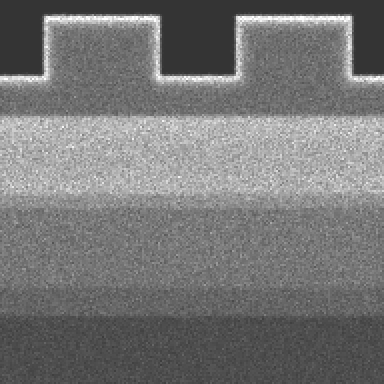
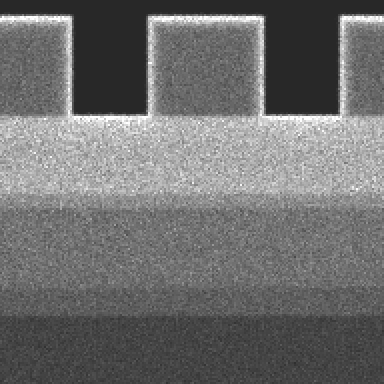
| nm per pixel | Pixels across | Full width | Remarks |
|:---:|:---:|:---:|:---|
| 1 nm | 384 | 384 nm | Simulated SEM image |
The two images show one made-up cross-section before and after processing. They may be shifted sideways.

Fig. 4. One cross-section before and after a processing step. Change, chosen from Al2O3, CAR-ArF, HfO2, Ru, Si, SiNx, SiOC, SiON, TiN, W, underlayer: underlayer removed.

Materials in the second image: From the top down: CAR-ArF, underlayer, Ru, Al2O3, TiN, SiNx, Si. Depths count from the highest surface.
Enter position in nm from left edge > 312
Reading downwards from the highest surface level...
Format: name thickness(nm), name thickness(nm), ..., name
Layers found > empty 100, Ru 78, Al2O3 14, TiN 80, SiNx 28, Si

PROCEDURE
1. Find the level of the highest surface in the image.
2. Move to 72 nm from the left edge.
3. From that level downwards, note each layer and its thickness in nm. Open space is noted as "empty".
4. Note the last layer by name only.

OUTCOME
empty 100, Ru 78, Al2O3 14, TiN 80, SiNx 28, Si